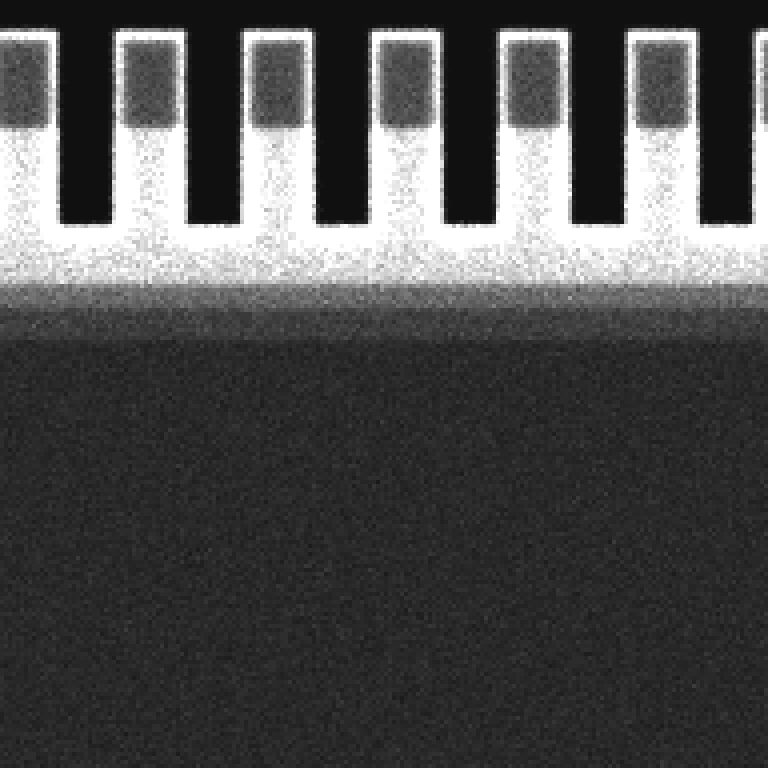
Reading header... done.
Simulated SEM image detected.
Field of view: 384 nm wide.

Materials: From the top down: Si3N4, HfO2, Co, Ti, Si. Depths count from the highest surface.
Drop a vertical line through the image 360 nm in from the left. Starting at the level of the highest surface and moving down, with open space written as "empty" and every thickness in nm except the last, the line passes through empty 98, HfO2 28, Co 12, Ti 16, Si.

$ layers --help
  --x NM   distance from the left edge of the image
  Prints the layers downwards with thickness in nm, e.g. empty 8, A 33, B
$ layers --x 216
Si3N4 48, HfO2 78, Co 12, Ti 16, Si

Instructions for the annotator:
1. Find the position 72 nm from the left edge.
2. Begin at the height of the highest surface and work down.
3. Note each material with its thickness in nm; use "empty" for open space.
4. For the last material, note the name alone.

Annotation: Si3N4 48, HfO2 78, Co 12, Ti 16, Si